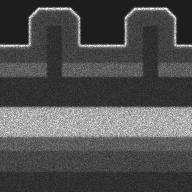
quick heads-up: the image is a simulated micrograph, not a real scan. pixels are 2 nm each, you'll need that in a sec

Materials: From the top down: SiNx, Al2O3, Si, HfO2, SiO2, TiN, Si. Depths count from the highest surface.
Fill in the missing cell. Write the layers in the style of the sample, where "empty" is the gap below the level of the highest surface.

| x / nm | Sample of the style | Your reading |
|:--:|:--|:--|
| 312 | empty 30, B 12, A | SiNx 36, Si 162, HfO2 60, SiO2 28, TiN 42, Si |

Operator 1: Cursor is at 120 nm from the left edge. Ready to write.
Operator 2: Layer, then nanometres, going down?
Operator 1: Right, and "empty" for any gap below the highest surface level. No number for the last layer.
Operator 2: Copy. SiNx 36, Si 162, HfO2 60, SiO2 28, TiN 42, Si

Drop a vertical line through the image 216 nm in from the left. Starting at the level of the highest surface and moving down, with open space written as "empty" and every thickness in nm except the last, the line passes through empty 74, SiNx 36, Al2O3 28, Si 60, HfO2 60, SiO2 28, TiN 42, Si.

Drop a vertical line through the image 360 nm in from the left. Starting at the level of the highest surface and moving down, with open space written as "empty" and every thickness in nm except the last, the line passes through empty 74, SiNx 36, Al2O3 28, Si 60, HfO2 60, SiO2 28, TiN 42, Si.